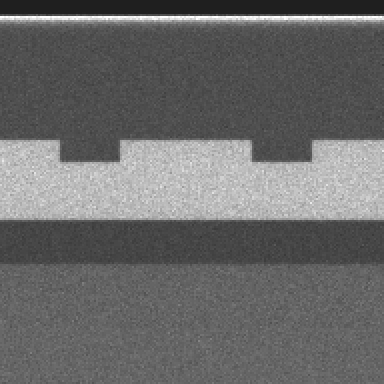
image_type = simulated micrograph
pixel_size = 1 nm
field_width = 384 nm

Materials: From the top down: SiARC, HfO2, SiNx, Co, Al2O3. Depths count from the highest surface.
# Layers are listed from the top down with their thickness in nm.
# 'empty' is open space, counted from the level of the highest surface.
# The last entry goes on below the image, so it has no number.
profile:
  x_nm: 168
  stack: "SiARC 124, HfO2 80, SiNx 44, Co 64, Al2O3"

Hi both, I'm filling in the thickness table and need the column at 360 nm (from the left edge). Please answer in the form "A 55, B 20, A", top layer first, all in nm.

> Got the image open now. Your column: SiARC 124, HfO2 80, SiNx 44, Co 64, Al2O3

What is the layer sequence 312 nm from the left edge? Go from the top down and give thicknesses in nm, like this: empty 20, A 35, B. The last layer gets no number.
SiARC 124, HfO2 80, SiNx 44, Co 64, Al2O3